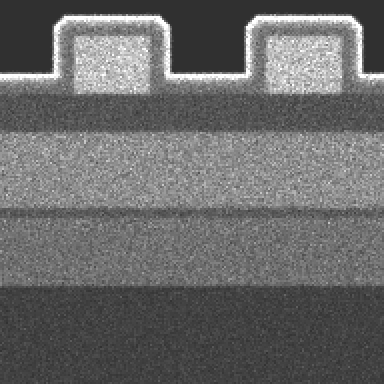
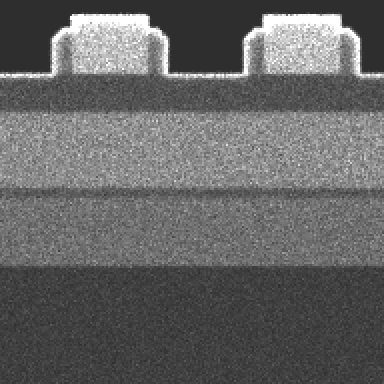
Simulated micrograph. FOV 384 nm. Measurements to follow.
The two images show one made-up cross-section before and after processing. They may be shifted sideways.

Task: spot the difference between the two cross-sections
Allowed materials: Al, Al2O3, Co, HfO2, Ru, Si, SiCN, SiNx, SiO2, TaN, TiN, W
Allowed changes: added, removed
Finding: removed SiO2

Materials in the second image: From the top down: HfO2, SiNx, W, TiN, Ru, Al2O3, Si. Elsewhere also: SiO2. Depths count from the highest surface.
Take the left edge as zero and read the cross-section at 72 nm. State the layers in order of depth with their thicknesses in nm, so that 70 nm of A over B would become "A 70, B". HfO2 58, SiNx 38, W 76, TiN 10, Ru 12, Al2O3 56, Si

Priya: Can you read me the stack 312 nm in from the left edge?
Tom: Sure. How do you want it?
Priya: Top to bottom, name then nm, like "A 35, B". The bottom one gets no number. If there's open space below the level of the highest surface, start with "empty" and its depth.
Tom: HfO2 58, SiNx 38, W 76, TiN 10, Ru 12, Al2O3 56, Si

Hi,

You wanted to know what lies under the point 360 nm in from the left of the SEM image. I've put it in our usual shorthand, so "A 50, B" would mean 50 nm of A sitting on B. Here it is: empty 58, SiNx 38, W 76, TiN 10, Ru 12, Al2O3 56, Si